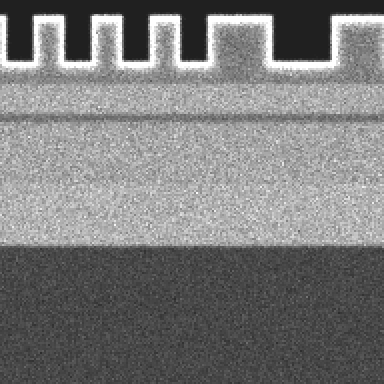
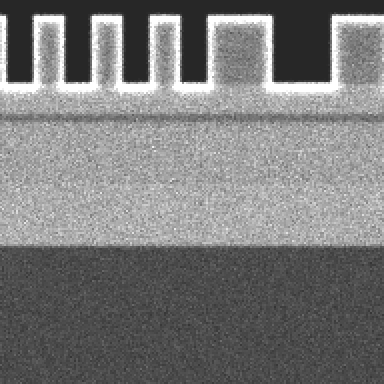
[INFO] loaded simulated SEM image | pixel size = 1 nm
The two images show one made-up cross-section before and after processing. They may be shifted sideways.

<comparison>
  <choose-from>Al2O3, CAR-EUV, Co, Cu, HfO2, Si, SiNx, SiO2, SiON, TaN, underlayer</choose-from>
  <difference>underlayer removed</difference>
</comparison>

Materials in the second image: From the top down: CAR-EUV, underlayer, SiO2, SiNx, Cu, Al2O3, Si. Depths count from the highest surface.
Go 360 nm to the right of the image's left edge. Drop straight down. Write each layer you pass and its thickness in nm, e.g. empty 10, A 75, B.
CAR-EUV 46, underlayer 22, SiO2 30, SiNx 8, Cu 62, Al2O3 62, Si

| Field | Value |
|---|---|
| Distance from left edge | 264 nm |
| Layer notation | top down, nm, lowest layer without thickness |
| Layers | CAR-EUV 46, underlayer 22, SiO2 30, SiNx 8, Cu 62, Al2O3 62, Si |